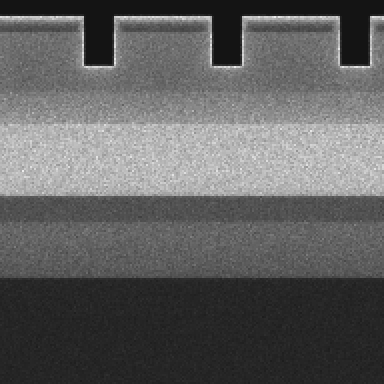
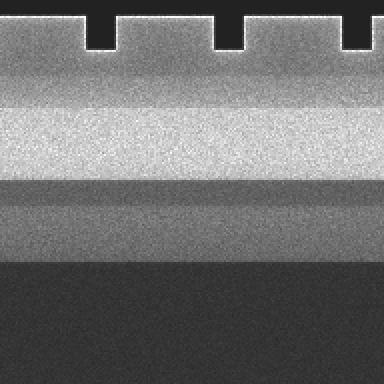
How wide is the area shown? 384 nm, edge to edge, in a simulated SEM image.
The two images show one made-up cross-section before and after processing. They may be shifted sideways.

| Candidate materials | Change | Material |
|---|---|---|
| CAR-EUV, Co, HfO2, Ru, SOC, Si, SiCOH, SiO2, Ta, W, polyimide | removed | SOC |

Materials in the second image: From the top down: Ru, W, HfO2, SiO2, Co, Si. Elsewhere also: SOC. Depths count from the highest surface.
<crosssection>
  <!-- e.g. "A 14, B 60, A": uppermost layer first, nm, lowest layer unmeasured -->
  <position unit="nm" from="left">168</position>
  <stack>Ru 60, W 32, HfO2 72, SiO2 26, Co 56, Si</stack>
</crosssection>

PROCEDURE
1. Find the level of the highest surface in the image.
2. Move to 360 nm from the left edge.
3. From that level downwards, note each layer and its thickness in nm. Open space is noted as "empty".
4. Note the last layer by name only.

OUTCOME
empty 34, Ru 26, W 32, HfO2 72, SiO2 26, Co 56, Si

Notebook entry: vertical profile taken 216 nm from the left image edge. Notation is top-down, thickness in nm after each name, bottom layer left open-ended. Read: empty 34, Ru 26, W 32, HfO2 72, SiO2 26, Co 56, Si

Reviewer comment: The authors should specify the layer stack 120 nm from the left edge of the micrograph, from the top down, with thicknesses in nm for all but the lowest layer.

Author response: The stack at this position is Ru 60, W 32, HfO2 72, SiO2 26, Co 56, Si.